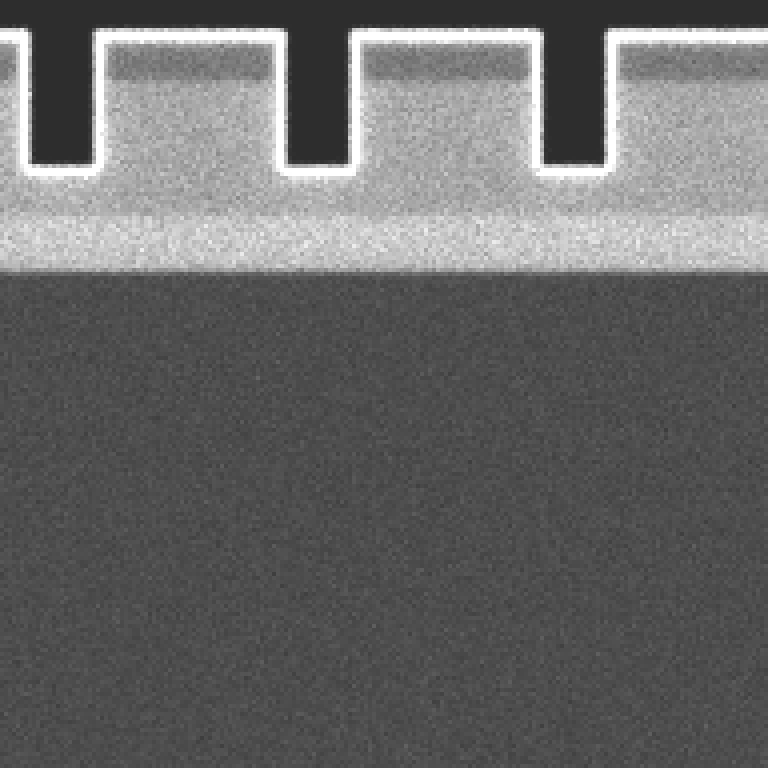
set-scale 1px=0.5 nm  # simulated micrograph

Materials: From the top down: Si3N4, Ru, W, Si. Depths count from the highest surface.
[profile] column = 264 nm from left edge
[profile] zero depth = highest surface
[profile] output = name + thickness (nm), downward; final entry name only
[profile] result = Si3N4 24, Ru 68, W 28, Si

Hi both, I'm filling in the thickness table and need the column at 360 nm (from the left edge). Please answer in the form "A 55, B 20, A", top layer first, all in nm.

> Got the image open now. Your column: Si3N4 24, Ru 68, W 28, Si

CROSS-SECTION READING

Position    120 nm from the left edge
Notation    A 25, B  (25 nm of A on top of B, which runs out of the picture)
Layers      Si3N4 24, Ru 68, W 28, Si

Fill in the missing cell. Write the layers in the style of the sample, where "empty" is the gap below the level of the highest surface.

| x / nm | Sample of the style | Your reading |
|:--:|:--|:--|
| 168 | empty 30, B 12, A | empty 68, Ru 24, W 28, Si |